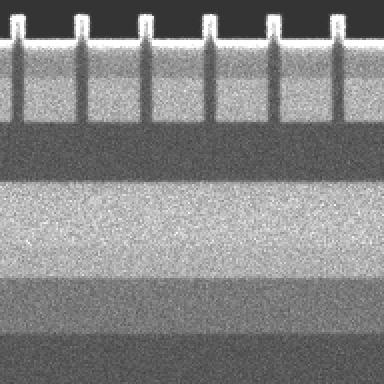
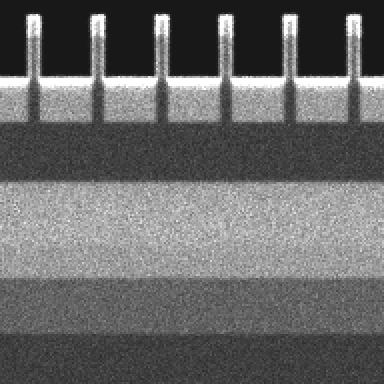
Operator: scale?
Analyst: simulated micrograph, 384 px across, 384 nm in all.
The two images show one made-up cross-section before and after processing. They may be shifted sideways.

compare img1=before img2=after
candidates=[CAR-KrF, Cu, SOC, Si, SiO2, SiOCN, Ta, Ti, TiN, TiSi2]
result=removed:SOC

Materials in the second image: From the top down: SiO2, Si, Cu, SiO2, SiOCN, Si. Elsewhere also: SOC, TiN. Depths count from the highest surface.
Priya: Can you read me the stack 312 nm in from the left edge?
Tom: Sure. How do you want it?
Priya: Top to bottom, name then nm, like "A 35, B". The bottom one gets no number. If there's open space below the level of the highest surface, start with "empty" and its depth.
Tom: empty 62, SiO2 44, Si 60, Cu 64, SiO2 32, SiOCN 56, Si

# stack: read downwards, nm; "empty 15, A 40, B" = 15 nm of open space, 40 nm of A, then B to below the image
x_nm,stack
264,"empty 62, SiO2 44, Si 60, Cu 64, SiO2 32, SiOCN 56, Si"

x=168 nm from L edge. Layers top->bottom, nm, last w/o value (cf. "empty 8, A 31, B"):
empty 62, SiO2 44, Si 60, Cu 64, SiO2 32, SiOCN 56, Si